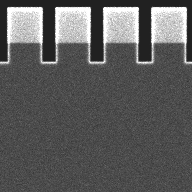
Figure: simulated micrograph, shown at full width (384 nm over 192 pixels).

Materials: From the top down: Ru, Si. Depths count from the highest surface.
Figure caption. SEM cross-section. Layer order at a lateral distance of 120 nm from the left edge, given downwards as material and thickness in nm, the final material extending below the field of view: Ru 70, Si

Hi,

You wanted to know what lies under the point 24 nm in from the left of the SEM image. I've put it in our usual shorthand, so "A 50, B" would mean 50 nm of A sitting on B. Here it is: Ru 70, Si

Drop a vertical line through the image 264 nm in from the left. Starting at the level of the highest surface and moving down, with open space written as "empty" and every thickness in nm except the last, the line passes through Ru 70, Si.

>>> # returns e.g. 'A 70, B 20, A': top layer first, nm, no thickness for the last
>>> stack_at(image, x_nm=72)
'Ru 70, Si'